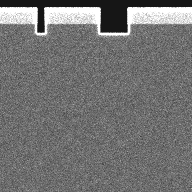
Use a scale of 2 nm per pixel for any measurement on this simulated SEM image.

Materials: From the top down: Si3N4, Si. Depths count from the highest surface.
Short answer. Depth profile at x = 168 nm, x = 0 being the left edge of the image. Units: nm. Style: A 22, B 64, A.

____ Si3N4 32, Si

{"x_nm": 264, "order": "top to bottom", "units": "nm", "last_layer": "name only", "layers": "Si3N4 32, Si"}